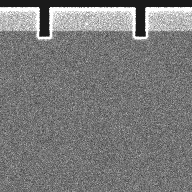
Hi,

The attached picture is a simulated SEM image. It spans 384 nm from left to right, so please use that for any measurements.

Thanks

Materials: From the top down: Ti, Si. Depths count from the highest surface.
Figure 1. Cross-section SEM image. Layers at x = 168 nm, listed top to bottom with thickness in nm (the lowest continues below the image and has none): Ti 46, Si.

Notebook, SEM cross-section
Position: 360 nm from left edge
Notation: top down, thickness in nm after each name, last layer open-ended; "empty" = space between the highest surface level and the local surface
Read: Ti 46, Si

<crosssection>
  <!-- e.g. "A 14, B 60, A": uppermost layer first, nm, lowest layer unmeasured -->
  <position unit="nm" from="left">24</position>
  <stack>Ti 46, Si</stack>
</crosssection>